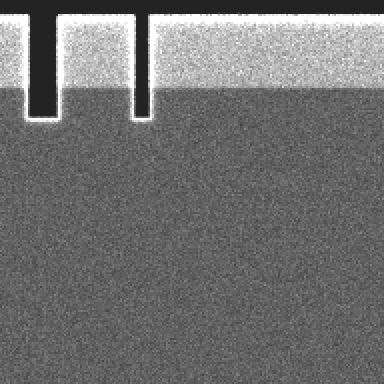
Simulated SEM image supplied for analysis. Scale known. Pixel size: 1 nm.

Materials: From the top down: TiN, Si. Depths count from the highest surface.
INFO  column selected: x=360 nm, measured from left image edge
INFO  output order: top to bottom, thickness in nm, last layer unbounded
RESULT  TiN 72, Si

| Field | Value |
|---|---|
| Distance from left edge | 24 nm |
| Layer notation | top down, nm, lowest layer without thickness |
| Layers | TiN 72, Si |